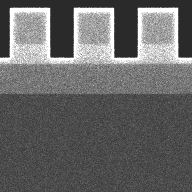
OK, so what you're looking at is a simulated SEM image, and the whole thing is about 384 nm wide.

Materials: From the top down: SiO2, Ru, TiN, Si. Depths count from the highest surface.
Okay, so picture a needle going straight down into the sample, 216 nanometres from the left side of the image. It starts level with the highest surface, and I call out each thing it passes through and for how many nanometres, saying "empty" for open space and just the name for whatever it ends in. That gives SiO2 72, Ru 40, TiN 60, Si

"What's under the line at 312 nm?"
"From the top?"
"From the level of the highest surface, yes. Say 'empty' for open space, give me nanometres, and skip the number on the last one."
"SiO2 72, Ru 40, TiN 60, Si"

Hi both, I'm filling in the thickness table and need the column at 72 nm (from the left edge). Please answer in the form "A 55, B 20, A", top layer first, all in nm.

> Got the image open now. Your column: SiO2 72, Ru 40, TiN 60, Si